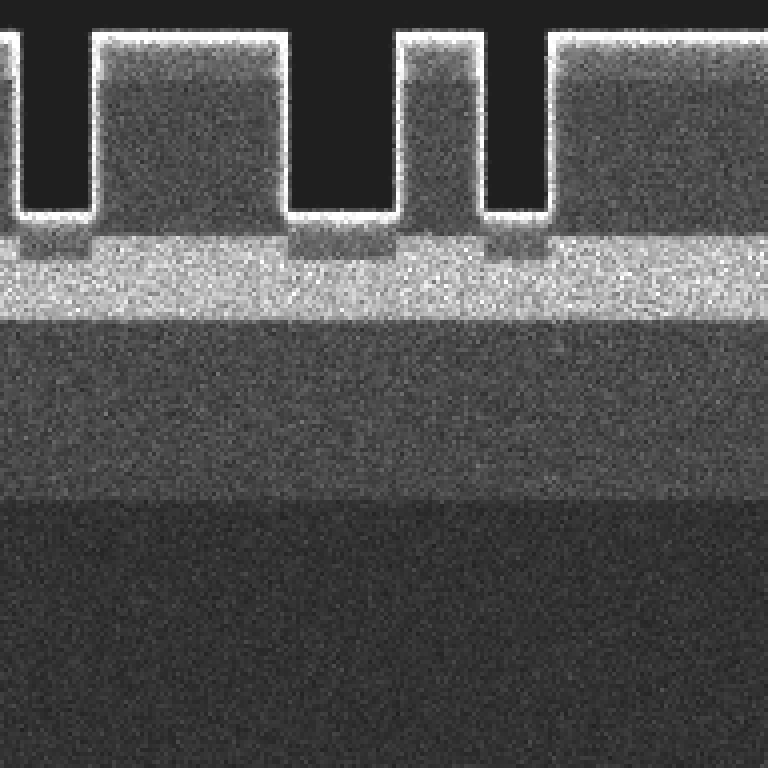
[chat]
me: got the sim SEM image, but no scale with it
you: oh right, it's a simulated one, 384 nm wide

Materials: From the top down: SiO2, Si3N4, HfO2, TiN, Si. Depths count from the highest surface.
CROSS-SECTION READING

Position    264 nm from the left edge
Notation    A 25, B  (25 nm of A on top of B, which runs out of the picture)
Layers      empty 90, SiO2 24, HfO2 30, TiN 90, Si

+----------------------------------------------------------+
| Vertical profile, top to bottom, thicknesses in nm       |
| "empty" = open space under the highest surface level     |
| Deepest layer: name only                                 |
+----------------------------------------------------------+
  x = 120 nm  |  SiO2 24, Si3N4 78, HfO2 42, TiN 90, Si